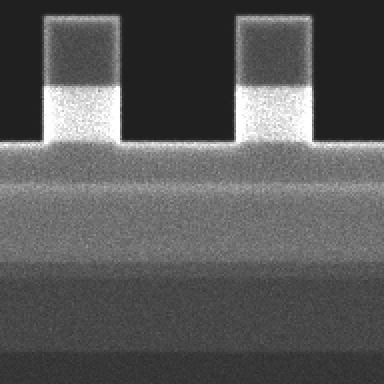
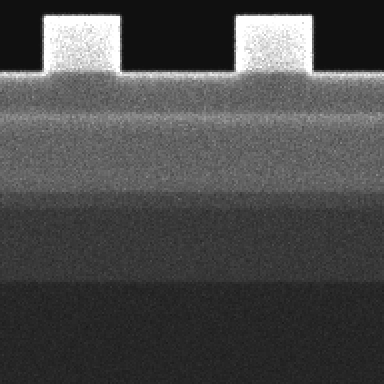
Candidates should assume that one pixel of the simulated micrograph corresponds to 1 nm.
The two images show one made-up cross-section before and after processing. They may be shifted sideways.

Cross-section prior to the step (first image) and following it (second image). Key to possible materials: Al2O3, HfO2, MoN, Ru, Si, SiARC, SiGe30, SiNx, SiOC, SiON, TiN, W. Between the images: SiARC was removed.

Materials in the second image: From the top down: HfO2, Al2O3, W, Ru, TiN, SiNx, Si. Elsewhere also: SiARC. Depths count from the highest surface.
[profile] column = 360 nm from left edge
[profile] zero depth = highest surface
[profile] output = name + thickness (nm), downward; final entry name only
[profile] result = empty 56, Al2O3 42, W 68, Ru 10, TiN 16, SiNx 74, Si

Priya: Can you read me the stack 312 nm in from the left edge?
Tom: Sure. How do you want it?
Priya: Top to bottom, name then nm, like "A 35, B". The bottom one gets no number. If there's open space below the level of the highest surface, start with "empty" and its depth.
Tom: empty 56, Al2O3 42, W 68, Ru 10, TiN 16, SiNx 74, Si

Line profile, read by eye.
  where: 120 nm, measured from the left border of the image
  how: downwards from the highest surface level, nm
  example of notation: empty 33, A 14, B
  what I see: empty 56, Al2O3 42, W 68, Ru 10, TiN 16, SiNx 74, Si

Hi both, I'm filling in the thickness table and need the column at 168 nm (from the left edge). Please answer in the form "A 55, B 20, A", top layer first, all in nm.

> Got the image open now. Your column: empty 56, Al2O3 42, W 68, Ru 10, TiN 16, SiNx 74, Si